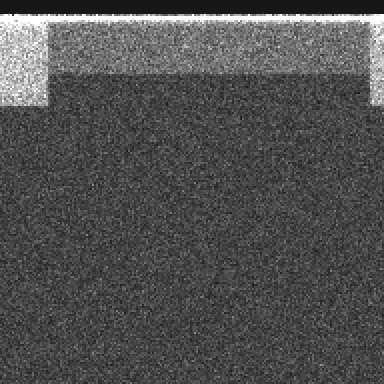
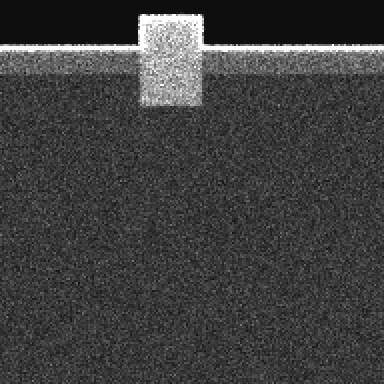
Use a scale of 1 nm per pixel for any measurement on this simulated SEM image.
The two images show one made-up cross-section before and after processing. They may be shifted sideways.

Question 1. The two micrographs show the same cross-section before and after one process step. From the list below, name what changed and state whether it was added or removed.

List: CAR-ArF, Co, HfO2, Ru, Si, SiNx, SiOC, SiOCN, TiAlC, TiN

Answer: SiNx, removed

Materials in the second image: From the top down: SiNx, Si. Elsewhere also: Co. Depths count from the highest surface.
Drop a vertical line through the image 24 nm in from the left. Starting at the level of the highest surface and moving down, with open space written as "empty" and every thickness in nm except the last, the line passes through empty 30, SiNx 28, Si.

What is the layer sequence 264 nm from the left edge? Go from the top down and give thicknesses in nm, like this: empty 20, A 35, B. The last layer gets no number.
empty 30, SiNx 28, Si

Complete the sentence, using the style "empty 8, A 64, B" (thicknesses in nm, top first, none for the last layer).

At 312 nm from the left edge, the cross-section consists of empty 30, SiNx 28, Si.